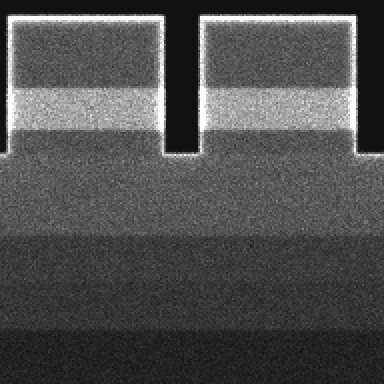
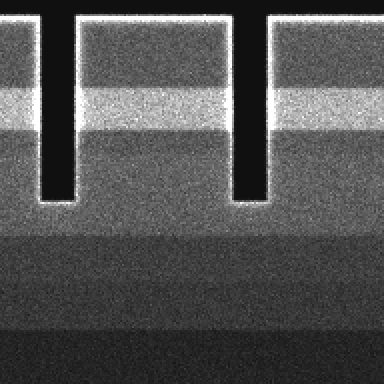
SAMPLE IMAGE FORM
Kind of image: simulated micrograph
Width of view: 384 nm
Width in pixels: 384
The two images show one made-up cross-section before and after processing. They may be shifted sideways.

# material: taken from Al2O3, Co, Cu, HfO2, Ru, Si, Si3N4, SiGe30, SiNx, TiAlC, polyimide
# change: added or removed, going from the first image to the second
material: Ru
change: removed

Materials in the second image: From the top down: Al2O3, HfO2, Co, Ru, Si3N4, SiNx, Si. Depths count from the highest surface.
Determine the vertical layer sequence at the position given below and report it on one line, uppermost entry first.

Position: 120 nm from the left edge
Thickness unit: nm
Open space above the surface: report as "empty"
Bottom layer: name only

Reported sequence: Al2O3 72, HfO2 42, Co 24, Ru 82, Si3N4 46, SiNx 48, Si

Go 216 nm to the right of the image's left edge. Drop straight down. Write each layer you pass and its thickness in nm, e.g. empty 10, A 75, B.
Al2O3 72, HfO2 42, Co 24, Ru 82, Si3N4 46, SiNx 48, Si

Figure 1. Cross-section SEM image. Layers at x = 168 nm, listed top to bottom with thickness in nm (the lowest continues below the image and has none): Al2O3 72, HfO2 42, Co 24, Ru 82, Si3N4 46, SiNx 48, Si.